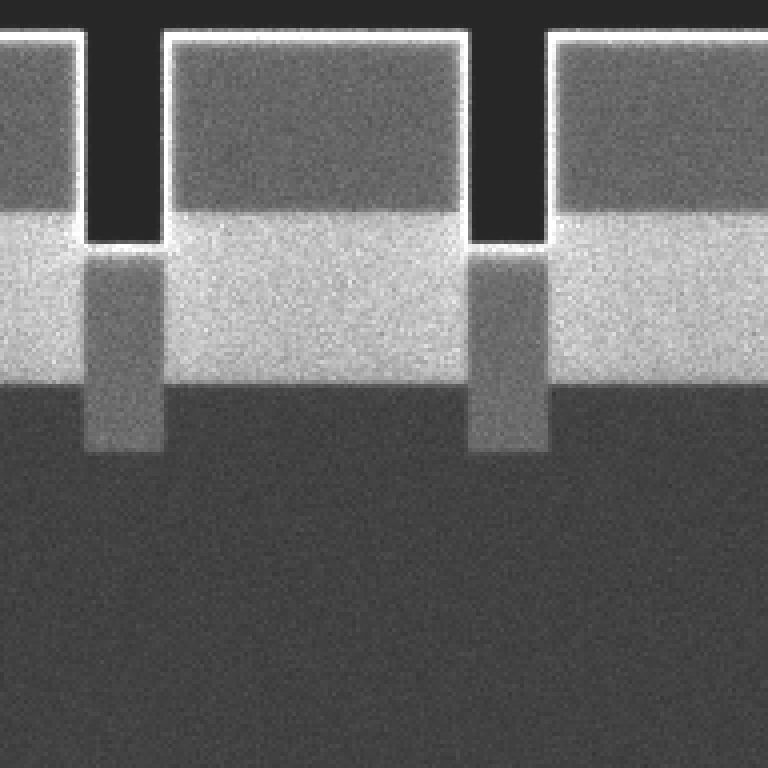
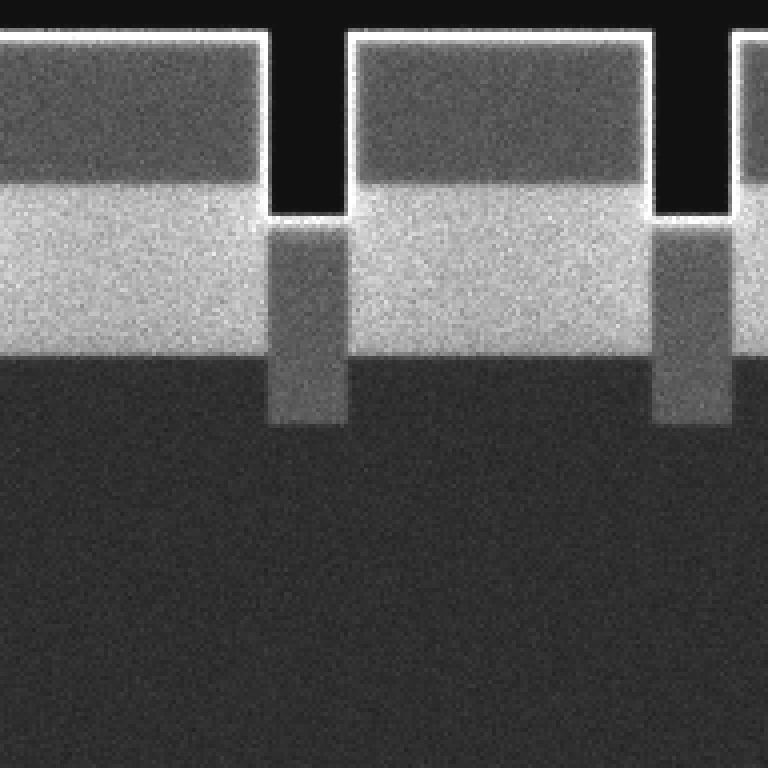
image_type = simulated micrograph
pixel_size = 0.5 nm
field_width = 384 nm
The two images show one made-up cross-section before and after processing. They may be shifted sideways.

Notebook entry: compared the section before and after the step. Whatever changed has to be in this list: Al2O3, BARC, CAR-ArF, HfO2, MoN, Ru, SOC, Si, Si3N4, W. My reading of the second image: Si3N4 removed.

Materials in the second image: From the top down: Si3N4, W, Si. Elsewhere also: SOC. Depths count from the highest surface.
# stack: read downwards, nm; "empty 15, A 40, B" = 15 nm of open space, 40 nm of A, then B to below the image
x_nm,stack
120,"Si3N4 76, W 86, Si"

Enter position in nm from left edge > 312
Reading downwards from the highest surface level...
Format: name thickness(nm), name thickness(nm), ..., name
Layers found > Si3N4 76, W 86, Si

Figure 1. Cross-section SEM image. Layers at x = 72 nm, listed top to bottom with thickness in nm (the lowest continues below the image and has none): Si3N4 76, W 86, Si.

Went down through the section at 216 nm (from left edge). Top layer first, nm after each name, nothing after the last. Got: Si3N4 76, W 86, Si